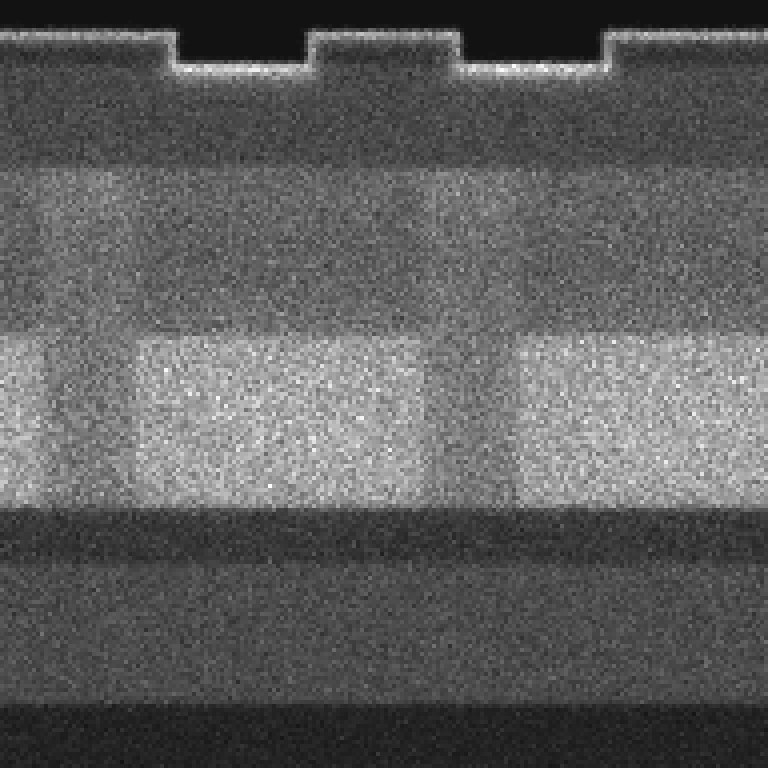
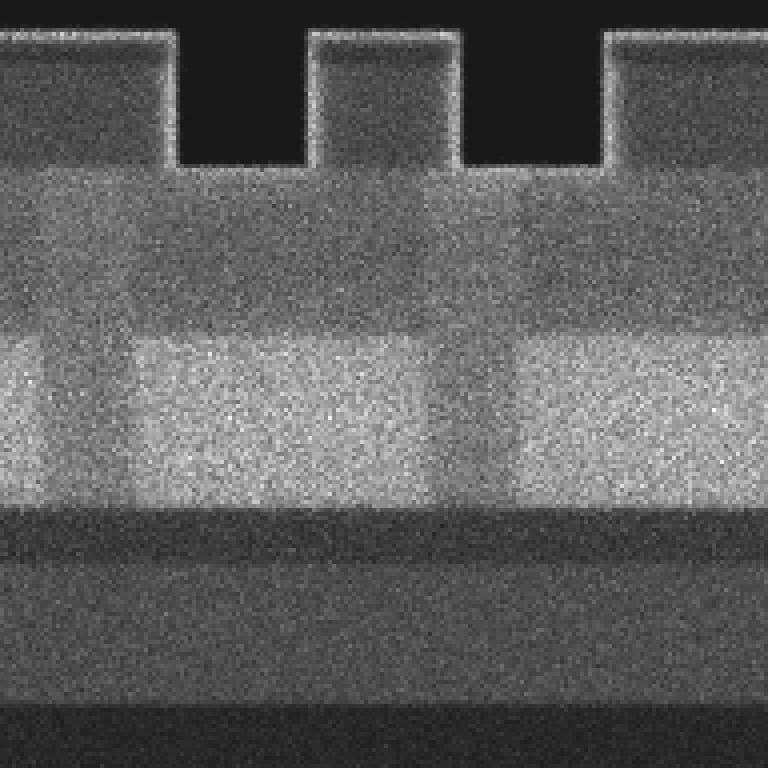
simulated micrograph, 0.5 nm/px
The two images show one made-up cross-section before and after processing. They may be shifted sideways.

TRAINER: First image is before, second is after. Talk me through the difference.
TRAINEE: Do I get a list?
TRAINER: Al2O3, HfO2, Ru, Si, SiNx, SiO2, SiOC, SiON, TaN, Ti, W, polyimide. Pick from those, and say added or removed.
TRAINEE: removed: SiO2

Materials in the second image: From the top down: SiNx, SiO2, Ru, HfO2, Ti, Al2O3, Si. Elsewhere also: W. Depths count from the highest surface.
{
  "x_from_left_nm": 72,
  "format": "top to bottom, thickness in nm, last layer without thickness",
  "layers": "SiNx 16, SiO2 52, Ru 84, HfO2 86, Ti 28, Al2O3 70, Si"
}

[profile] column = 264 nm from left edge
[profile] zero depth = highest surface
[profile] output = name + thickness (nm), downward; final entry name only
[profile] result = empty 68, Ru 84, HfO2 86, Ti 28, Al2O3 70, Si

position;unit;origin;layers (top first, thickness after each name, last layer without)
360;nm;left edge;SiNx 16, SiO2 52, Ru 84, HfO2 86, Ti 28, Al2O3 70, Si